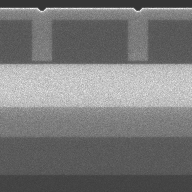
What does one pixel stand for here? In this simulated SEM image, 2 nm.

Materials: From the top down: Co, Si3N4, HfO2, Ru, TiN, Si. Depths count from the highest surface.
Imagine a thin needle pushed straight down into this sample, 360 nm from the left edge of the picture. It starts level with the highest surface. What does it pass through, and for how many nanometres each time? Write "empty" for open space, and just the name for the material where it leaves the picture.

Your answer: Co 24, Si3N4 88, HfO2 86, Ru 60, TiN 76, Si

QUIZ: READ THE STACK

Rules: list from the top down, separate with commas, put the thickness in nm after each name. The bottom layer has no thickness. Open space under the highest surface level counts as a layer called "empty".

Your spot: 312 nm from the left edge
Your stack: Co 24, Si3N4 88, HfO2 86, Ru 60, TiN 76, Si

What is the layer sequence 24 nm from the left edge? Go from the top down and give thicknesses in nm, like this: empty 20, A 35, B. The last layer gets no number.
Co 24, Si3N4 88, HfO2 86, Ru 60, TiN 76, Si